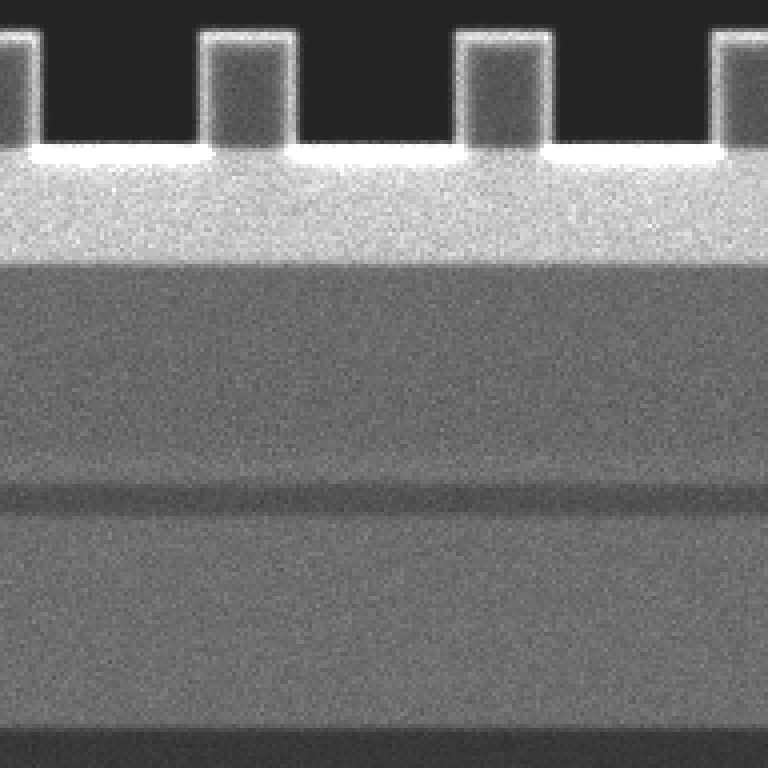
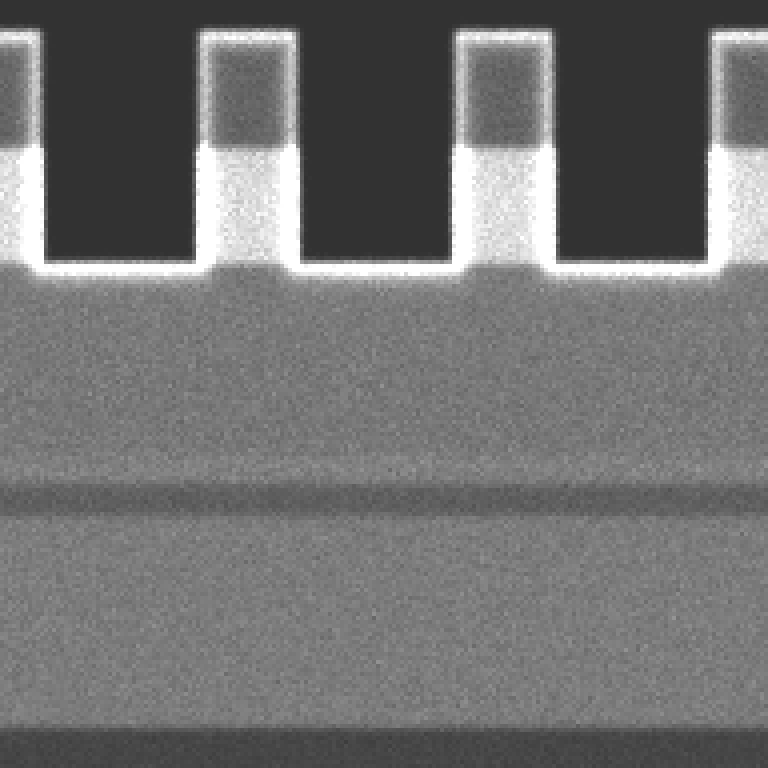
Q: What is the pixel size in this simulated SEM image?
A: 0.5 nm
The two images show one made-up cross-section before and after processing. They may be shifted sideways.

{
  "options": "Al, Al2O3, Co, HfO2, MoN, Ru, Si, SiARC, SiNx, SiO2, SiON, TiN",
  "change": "removed",
  "material": "HfO2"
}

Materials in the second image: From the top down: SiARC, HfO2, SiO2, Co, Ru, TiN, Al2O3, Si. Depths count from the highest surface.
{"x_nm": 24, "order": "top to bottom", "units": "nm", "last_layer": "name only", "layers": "empty 116, SiO2 44, Co 52, Ru 14, TiN 16, Al2O3 106, Si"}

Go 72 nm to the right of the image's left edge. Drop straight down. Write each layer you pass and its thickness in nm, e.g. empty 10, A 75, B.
empty 116, SiO2 44, Co 52, Ru 14, TiN 16, Al2O3 106, Si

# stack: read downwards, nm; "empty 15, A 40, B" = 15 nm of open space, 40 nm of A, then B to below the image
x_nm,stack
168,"empty 116, SiO2 44, Co 52, Ru 14, TiN 16, Al2O3 106, Si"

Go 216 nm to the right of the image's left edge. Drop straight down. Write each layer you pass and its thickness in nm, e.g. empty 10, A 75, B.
empty 116, SiO2 44, Co 52, Ru 14, TiN 16, Al2O3 106, Si